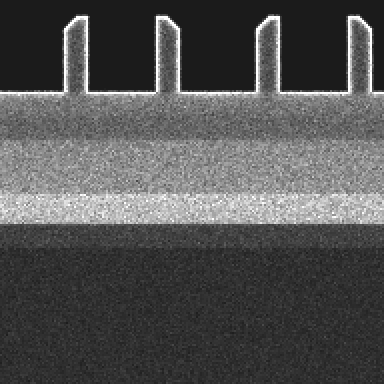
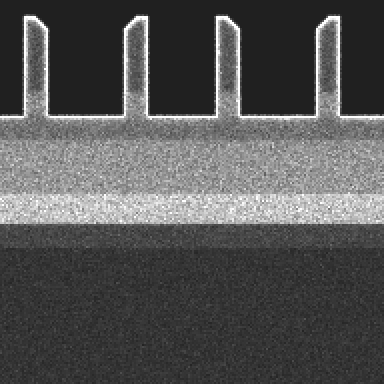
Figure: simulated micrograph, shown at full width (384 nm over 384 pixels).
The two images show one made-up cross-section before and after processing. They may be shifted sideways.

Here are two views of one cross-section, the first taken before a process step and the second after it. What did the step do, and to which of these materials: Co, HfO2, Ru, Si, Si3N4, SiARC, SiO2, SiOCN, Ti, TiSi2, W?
It removed Ru.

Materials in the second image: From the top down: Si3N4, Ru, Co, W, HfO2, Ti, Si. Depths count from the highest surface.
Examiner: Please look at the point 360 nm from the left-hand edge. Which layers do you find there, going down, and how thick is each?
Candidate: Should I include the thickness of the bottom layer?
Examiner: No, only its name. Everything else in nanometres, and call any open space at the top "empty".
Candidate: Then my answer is empty 100, Co 24, W 54, HfO2 30, Ti 24, Si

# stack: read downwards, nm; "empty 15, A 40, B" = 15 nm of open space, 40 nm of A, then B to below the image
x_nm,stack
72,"empty 100, Co 24, W 54, HfO2 30, Ti 24, Si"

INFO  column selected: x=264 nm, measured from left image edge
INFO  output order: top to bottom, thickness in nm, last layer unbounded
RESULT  empty 100, Co 24, W 54, HfO2 30, Ti 24, Si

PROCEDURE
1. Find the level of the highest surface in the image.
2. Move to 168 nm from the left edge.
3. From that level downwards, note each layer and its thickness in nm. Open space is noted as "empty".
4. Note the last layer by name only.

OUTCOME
empty 100, Co 24, W 54, HfO2 30, Ti 24, Si